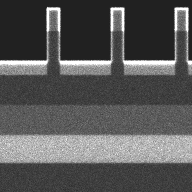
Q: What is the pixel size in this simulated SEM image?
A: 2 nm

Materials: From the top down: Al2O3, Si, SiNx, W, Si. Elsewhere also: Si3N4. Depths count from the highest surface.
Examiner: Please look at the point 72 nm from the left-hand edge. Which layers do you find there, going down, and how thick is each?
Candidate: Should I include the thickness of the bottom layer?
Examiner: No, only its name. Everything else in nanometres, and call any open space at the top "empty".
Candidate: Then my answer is empty 106, Al2O3 28, Si 60, SiNx 60, W 56, Si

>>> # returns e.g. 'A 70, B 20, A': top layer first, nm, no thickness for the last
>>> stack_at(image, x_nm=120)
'empty 106, Al2O3 28, Si 60, SiNx 60, W 56, Si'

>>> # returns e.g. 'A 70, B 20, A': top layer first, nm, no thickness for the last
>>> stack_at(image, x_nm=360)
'Si3N4 46, Si 148, SiNx 60, W 56, Si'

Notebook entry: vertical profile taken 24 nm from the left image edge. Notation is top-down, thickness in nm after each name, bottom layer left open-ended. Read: empty 106, Al2O3 28, Si 60, SiNx 60, W 56, Si